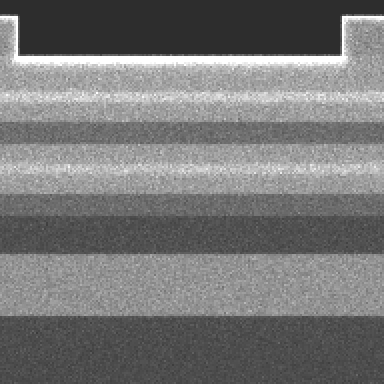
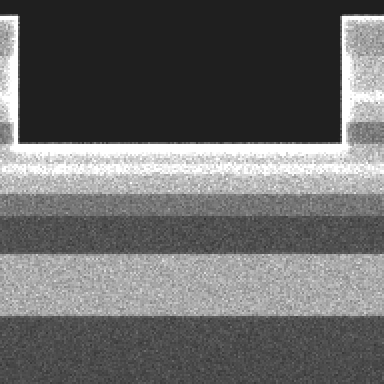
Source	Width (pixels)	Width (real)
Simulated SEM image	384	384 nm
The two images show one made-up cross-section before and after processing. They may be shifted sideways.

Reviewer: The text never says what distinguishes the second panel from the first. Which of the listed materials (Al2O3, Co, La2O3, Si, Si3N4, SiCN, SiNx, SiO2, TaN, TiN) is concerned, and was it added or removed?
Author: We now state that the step removed Al2O3 and Co and SiNx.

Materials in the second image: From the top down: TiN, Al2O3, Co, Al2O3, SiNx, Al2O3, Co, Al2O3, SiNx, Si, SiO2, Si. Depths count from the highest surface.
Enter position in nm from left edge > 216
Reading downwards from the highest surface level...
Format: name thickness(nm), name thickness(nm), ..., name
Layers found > empty 128, Al2O3 20, Co 10, Al2O3 20, SiNx 22, Si 38, SiO2 62, Si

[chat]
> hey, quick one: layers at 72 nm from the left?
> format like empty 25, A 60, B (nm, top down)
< empty 128, Al2O3 20, Co 10, Al2O3 20, SiNx 22, Si 38, SiO2 62, Si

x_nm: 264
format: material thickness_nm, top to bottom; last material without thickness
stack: empty 128, Al2O3 20, Co 10, Al2O3 20, SiNx 22, Si 38, SiO2 62, Si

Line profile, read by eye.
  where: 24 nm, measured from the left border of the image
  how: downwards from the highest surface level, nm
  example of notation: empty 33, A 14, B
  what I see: empty 128, Al2O3 20, Co 10, Al2O3 20, SiNx 22, Si 38, SiO2 62, Si